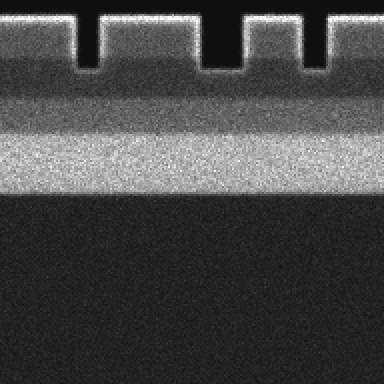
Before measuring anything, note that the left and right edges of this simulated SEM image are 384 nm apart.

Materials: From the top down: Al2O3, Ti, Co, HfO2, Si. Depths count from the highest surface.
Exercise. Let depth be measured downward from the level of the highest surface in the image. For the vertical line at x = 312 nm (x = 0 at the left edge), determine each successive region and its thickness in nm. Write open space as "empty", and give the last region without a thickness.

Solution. empty 54, Ti 28, Co 36, HfO2 60, Si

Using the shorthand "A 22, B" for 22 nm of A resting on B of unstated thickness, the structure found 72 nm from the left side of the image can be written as Al2O3 42, Ti 40, Co 36, HfO2 60, Si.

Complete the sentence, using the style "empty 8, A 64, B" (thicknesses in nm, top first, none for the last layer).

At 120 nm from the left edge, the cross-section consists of Al2O3 42, Ti 40, Co 36, HfO2 60, Si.